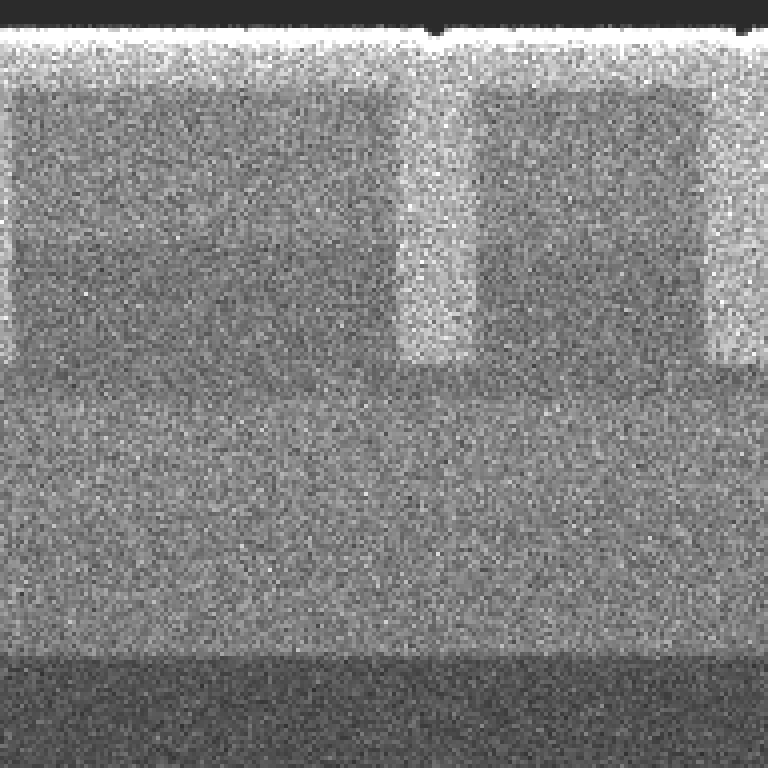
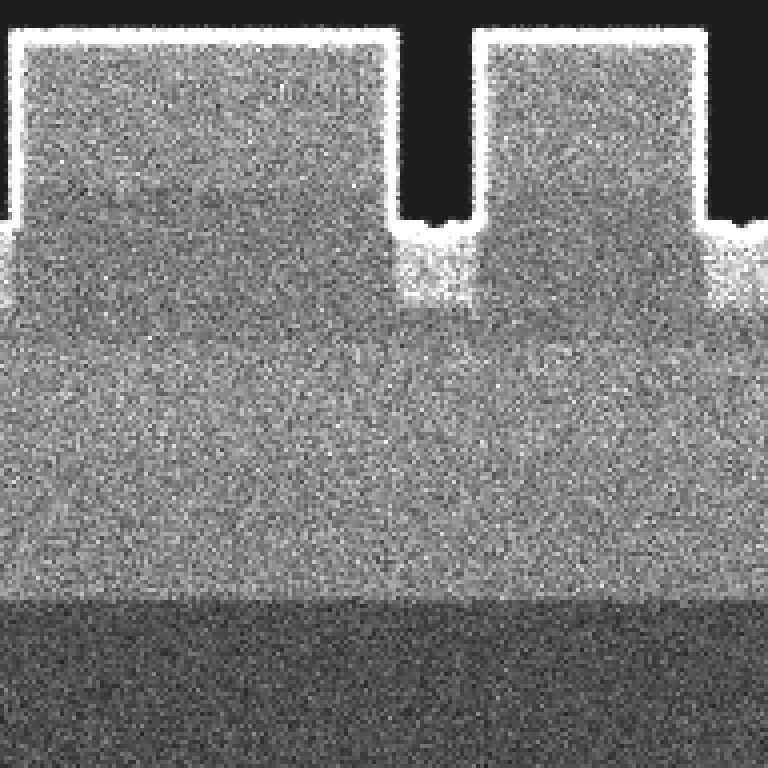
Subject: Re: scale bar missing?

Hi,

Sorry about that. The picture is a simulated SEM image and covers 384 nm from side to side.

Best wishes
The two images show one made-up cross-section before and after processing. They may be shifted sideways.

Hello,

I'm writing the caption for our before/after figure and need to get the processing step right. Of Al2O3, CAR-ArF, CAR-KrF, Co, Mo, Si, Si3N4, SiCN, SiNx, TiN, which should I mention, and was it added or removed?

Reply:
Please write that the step removed Co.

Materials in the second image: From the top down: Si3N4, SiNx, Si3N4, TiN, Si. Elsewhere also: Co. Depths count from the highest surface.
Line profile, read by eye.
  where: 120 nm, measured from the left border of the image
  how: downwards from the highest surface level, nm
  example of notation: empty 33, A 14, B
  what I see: Si3N4 78, SiNx 78, Si3N4 54, TiN 74, Si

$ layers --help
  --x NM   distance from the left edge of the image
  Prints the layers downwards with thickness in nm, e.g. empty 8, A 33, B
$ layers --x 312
Si3N4 78, SiNx 78, Si3N4 54, TiN 74, Si